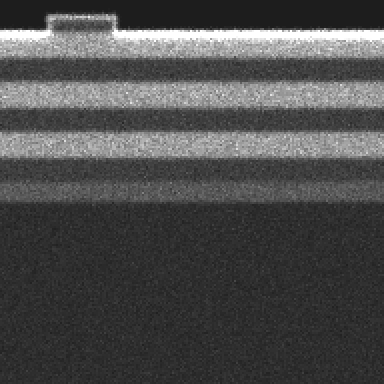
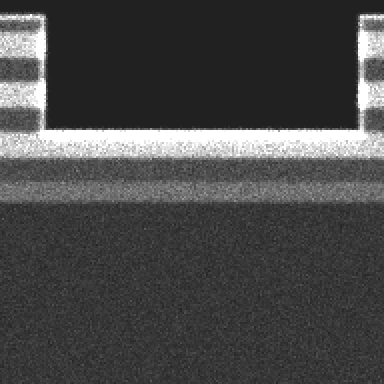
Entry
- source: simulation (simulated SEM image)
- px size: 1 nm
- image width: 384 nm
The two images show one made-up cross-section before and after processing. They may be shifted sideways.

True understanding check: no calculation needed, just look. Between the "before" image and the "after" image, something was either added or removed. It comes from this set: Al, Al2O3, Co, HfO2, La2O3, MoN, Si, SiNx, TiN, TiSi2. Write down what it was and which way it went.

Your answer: HfO2 and SiNx (removed)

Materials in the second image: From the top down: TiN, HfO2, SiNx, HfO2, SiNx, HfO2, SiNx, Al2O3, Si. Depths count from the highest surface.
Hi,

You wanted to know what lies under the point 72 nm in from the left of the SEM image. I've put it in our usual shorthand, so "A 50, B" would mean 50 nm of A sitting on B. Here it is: empty 116, HfO2 26, SiNx 24, Al2O3 20, Si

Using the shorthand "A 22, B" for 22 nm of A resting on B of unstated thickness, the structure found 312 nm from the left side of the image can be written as empty 116, HfO2 26, SiNx 24, Al2O3 20, Si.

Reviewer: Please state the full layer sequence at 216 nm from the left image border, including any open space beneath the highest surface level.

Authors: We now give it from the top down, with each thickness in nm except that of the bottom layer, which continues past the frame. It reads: empty 116, HfO2 26, SiNx 24, Al2O3 20, Si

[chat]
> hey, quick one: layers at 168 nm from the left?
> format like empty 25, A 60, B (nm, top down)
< empty 116, HfO2 26, SiNx 24, Al2O3 20, Si